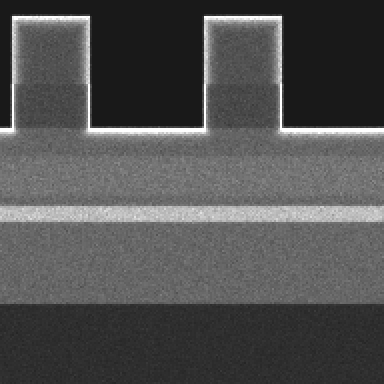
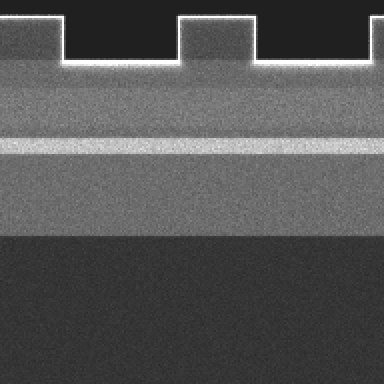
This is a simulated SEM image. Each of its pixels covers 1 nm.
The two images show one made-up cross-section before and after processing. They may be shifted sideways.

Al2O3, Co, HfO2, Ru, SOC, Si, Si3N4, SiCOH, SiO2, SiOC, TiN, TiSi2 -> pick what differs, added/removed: SOC removed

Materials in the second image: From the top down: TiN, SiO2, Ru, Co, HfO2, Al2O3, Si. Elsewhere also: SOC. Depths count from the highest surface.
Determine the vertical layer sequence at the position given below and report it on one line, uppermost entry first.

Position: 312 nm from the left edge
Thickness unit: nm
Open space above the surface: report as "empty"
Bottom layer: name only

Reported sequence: empty 44, SiO2 28, Ru 40, Co 10, HfO2 16, Al2O3 82, Si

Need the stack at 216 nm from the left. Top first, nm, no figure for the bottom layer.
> TiN 44, SiO2 28, Ru 40, Co 10, HfO2 16, Al2O3 82, Si